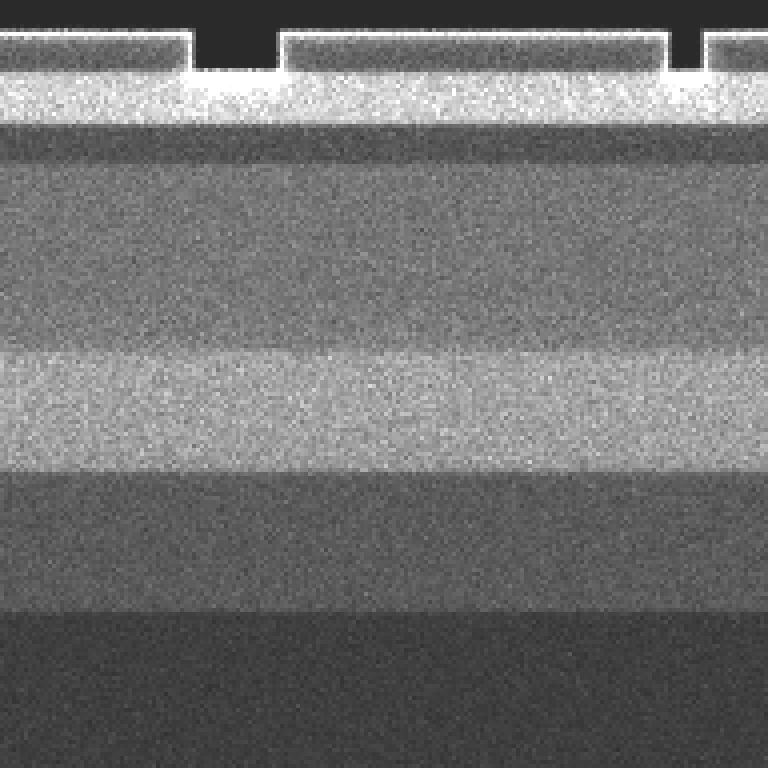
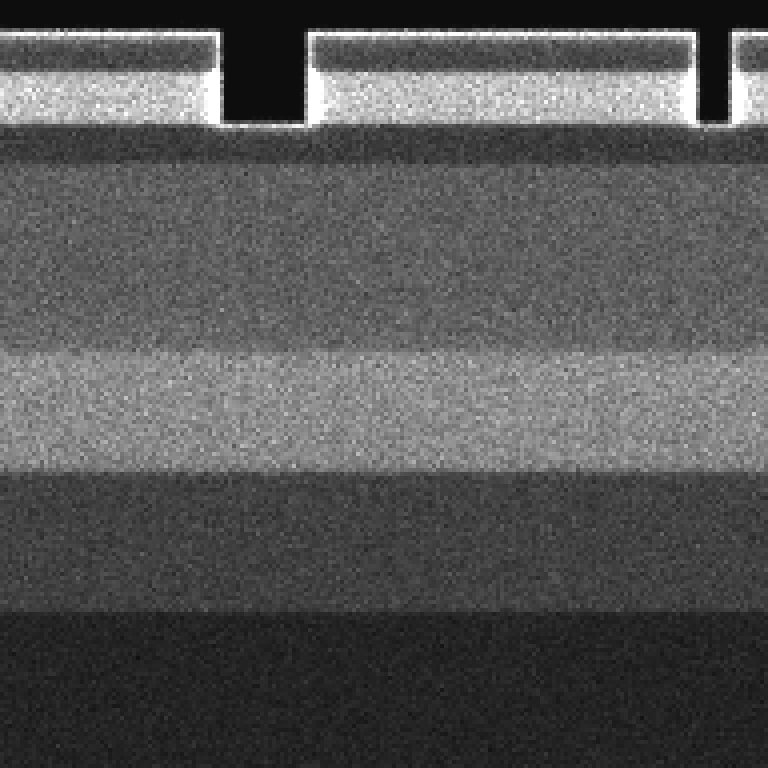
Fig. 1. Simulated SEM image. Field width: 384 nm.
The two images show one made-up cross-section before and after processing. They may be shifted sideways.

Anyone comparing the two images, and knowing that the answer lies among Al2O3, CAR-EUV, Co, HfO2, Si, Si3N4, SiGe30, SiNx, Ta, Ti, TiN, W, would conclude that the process removed HfO2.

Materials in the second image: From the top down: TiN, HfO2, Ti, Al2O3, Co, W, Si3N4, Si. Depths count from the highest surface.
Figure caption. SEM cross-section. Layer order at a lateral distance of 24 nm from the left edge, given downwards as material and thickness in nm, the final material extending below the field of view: TiN 20, HfO2 26, Ti 20, Al2O3 70, Co 24, W 60, Si3N4 70, Si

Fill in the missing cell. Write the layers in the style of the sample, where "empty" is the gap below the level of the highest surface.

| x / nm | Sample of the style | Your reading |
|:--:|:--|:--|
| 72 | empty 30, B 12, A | TiN 20, HfO2 26, Ti 20, Al2O3 70, Co 24, W 60, Si3N4 70, Si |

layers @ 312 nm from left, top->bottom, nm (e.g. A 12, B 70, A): TiN 20, HfO2 26, Ti 20, Al2O3 70, Co 24, W 60, Si3N4 70, Si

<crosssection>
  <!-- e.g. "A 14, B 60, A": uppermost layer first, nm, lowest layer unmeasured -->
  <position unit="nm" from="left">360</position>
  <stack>empty 46, Ti 20, Al2O3 70, Co 24, W 60, Si3N4 70, Si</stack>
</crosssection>